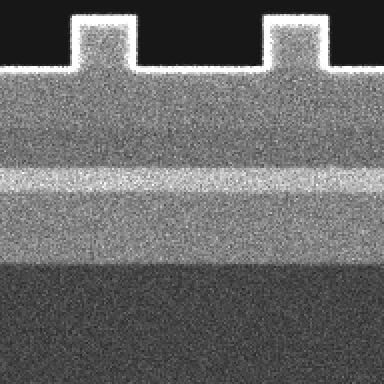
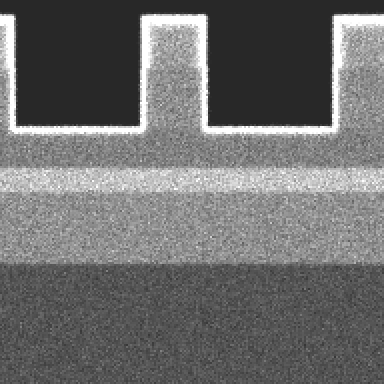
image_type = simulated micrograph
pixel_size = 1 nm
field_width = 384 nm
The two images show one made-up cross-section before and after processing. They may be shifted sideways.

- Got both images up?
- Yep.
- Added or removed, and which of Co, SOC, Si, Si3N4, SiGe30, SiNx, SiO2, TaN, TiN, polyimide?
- removed, TiN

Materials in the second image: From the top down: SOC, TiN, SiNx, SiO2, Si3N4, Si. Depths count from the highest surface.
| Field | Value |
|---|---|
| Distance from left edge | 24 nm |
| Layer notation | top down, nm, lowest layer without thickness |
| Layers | empty 112, SiNx 40, SiO2 24, Si3N4 72, Si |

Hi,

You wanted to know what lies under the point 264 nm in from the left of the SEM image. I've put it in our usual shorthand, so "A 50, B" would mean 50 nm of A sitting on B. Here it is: empty 112, SiNx 40, SiO2 24, Si3N4 72, Si